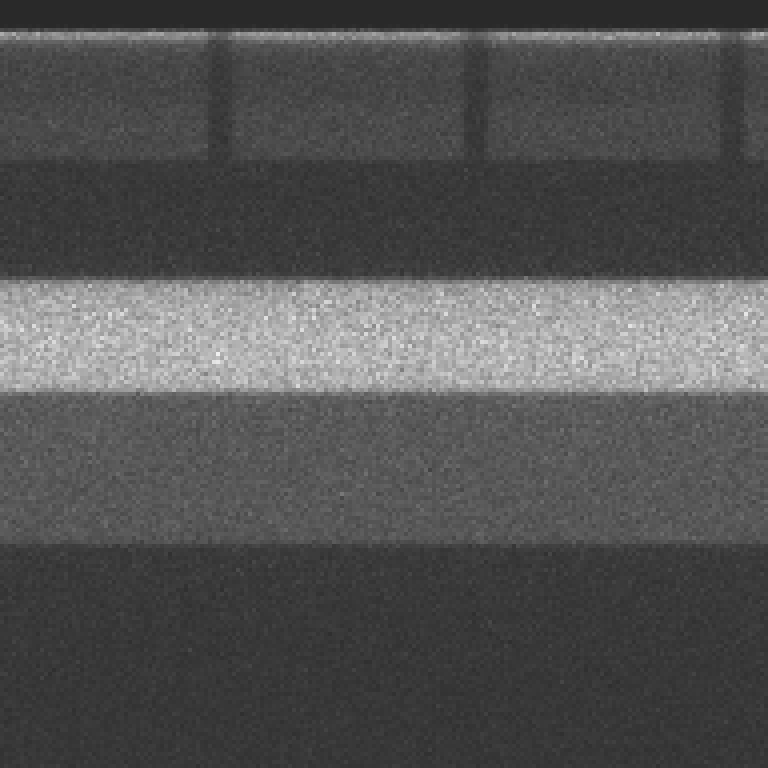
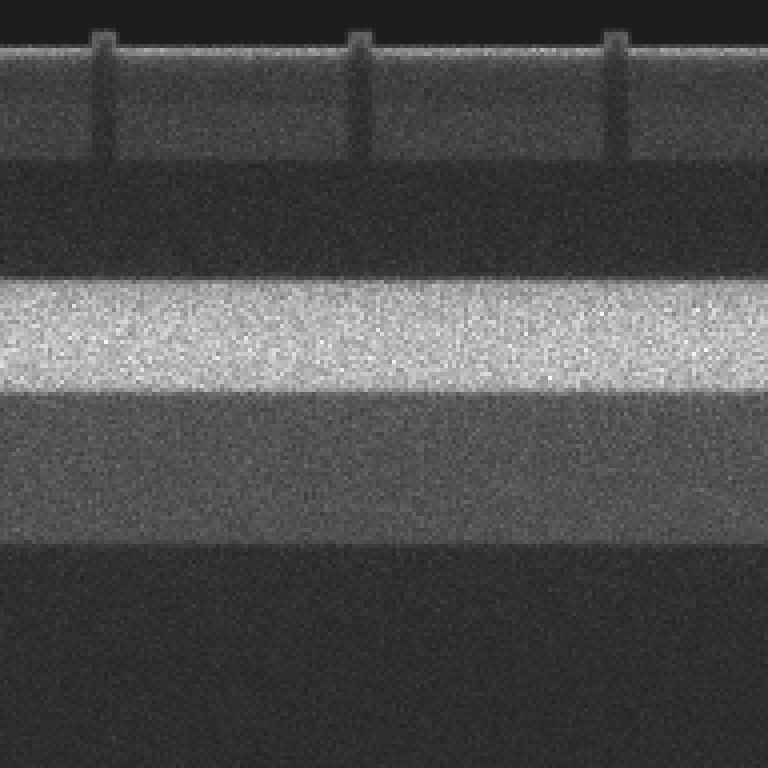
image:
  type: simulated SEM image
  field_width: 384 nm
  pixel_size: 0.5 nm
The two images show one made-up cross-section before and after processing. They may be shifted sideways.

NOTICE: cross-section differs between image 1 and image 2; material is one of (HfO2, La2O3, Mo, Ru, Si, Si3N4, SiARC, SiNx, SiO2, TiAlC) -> removed: SiNx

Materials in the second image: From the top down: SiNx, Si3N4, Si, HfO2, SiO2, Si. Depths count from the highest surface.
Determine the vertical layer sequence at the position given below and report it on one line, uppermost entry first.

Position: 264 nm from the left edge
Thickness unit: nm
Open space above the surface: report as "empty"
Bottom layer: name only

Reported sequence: empty 8, SiNx 28, Si3N4 28, Si 60, HfO2 56, SiO2 76, Si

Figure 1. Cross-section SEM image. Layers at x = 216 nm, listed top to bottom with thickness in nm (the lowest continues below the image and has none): empty 8, SiNx 28, Si3N4 28, Si 60, HfO2 56, SiO2 76, Si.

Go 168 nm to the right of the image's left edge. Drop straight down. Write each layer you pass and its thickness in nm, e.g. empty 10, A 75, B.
empty 8, SiNx 28, Si3N4 28, Si 60, HfO2 56, SiO2 76, Si